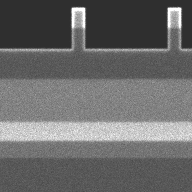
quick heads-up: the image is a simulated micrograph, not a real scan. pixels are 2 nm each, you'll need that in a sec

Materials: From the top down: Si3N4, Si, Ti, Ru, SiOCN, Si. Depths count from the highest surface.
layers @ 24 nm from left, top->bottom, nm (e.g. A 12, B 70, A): empty 82, Si 60, Ti 86, Ru 38, SiOCN 34, Si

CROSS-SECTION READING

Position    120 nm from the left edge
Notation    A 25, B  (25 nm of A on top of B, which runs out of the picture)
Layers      empty 82, Si 60, Ti 86, Ru 38, SiOCN 34, Si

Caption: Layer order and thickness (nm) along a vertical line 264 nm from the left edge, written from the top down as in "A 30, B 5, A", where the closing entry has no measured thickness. empty 82, Si 60, Ti 86, Ru 38, SiOCN 34, Si